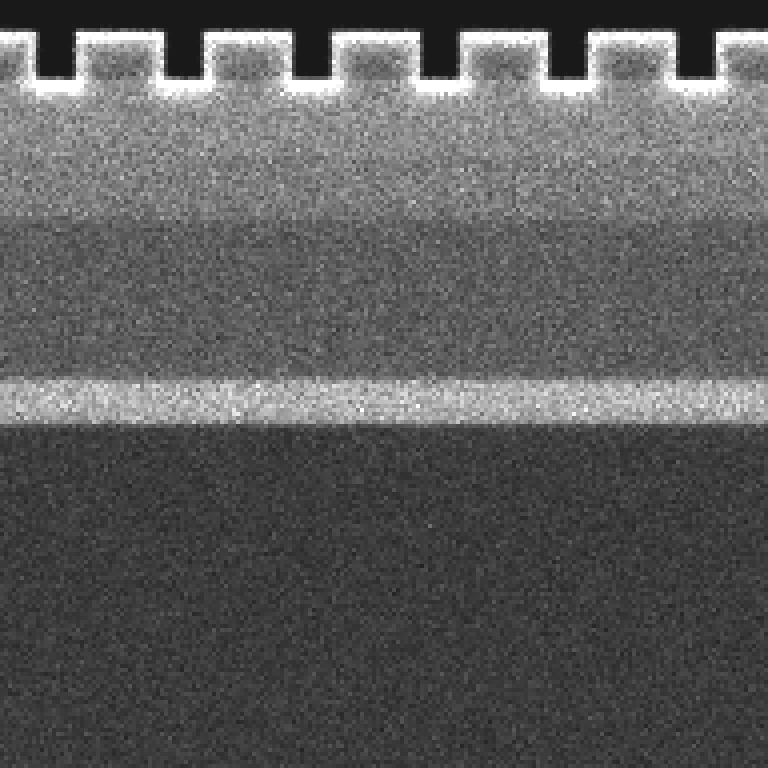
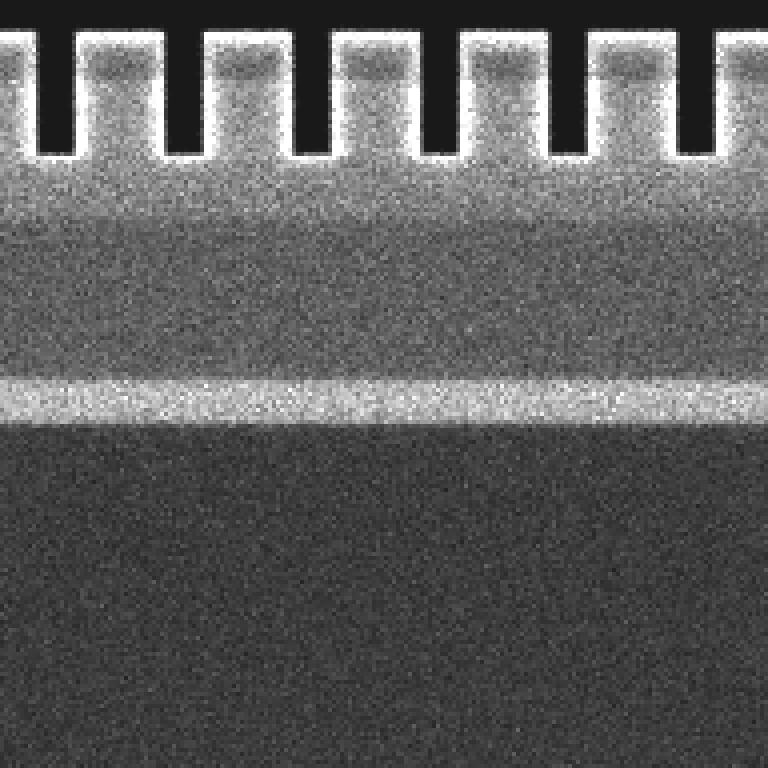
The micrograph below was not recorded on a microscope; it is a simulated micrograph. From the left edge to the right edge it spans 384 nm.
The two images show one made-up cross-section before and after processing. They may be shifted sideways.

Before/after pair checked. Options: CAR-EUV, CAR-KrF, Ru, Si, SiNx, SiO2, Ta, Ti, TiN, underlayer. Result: removed SiO2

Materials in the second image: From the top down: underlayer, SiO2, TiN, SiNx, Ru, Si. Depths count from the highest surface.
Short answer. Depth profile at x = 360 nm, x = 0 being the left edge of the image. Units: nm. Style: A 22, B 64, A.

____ underlayer 24, SiO2 38, TiN 32, SiNx 80, Ru 22, Si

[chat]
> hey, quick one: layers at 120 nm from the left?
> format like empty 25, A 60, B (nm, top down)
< underlayer 24, SiO2 38, TiN 32, SiNx 80, Ru 22, Si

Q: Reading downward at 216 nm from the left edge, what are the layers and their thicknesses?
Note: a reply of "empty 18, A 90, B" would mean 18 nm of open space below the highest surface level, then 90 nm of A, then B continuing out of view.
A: empty 62, TiN 32, SiNx 80, Ru 22, Si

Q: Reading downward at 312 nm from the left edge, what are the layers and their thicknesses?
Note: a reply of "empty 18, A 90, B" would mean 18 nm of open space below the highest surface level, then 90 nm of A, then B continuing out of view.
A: underlayer 24, SiO2 38, TiN 32, SiNx 80, Ru 22, Si